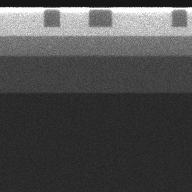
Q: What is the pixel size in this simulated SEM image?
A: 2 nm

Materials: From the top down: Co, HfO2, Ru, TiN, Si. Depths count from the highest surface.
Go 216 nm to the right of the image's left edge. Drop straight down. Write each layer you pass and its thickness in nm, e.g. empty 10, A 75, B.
Co 38, HfO2 18, Ru 40, TiN 74, Si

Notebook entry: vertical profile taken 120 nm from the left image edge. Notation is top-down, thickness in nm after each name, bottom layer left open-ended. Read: HfO2 56, Ru 40, TiN 74, Si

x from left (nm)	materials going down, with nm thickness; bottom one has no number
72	HfO2 56, Ru 40, TiN 74, Si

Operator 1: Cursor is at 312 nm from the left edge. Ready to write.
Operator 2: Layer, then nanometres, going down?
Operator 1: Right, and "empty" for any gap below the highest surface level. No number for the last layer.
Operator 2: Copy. HfO2 56, Ru 40, TiN 74, Si